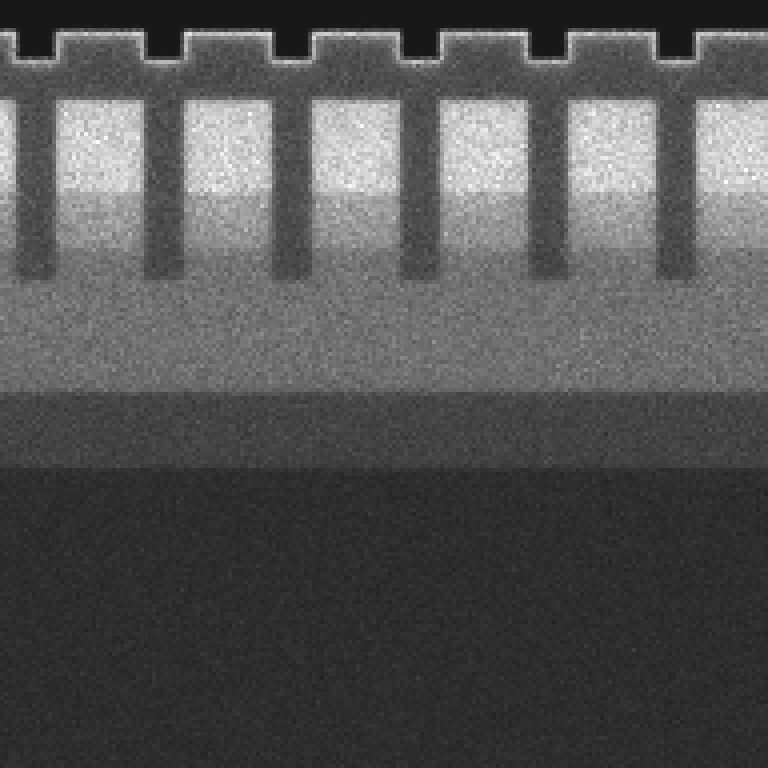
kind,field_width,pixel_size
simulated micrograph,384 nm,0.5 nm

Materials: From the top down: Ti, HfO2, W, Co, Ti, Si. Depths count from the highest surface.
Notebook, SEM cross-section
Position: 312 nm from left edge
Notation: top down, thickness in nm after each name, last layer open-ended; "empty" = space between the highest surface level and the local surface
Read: Ti 34, HfO2 46, W 28, Co 72, Ti 38, Si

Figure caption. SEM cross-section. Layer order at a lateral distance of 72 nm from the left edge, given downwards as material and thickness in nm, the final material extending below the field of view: empty 14, Ti 110, Co 56, Ti 38, Si